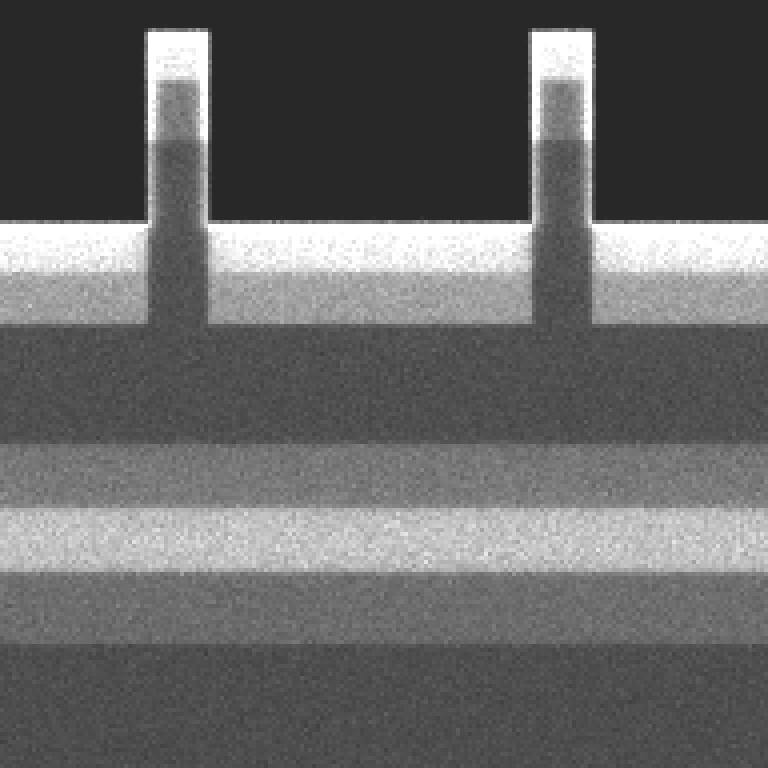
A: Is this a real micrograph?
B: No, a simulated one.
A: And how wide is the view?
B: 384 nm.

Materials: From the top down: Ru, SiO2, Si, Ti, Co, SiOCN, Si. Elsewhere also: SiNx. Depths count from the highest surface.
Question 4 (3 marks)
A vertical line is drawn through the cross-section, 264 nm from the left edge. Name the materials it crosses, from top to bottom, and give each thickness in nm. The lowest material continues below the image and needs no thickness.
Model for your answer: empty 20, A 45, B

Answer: empty 96, Ru 24, SiO2 26, Si 60, Ti 32, Co 32, SiOCN 36, Si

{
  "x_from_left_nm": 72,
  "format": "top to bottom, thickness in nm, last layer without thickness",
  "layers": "empty 96, Ru 24, SiO2 26, Si 60, Ti 32, Co 32, SiOCN 36, Si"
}